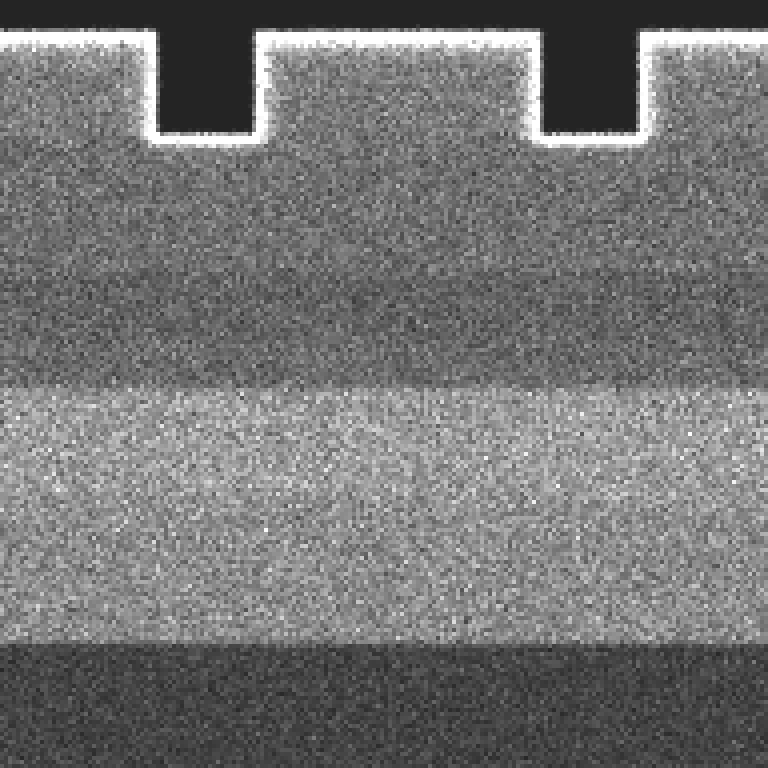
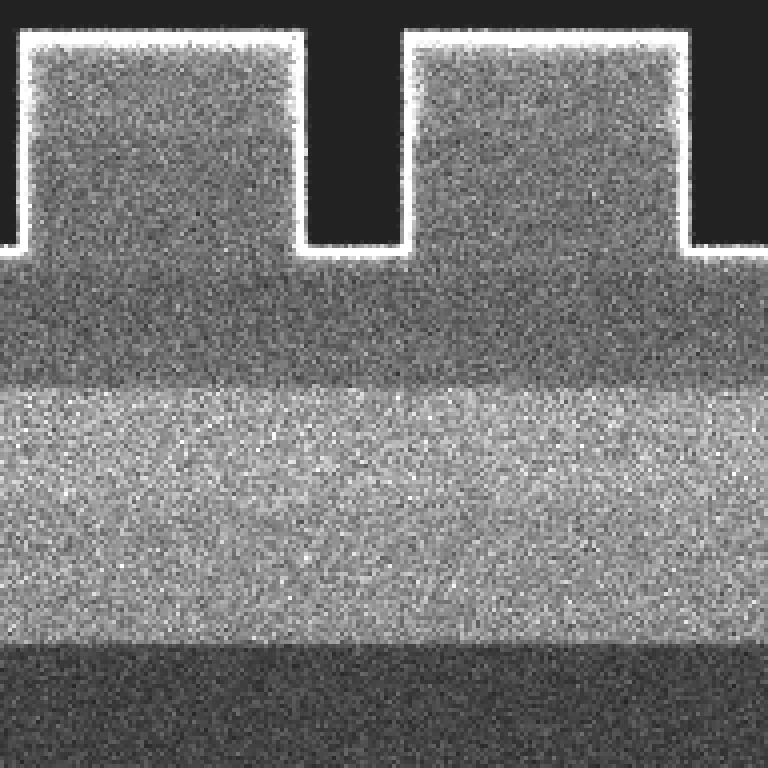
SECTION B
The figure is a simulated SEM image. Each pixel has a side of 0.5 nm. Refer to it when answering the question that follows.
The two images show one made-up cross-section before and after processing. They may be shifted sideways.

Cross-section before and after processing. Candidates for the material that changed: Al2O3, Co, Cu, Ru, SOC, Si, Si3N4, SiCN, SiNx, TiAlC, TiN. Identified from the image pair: Si3N4 (removed).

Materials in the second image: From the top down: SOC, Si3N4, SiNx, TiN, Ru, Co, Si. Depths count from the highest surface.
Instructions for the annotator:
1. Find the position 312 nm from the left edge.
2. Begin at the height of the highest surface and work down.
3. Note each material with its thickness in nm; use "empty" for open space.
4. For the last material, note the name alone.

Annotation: SOC 52, Si3N4 68, SiNx 34, TiN 24, Ru 56, Co 72, Si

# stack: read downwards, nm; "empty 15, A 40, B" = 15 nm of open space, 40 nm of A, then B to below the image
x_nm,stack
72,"SOC 52, Si3N4 68, SiNx 34, TiN 24, Ru 56, Co 72, Si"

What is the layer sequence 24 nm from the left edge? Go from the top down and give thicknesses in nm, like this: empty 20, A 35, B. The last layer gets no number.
SOC 52, Si3N4 68, SiNx 34, TiN 24, Ru 56, Co 72, Si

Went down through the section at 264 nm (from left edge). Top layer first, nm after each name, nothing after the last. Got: SOC 52, Si3N4 68, SiNx 34, TiN 24, Ru 56, Co 72, Si